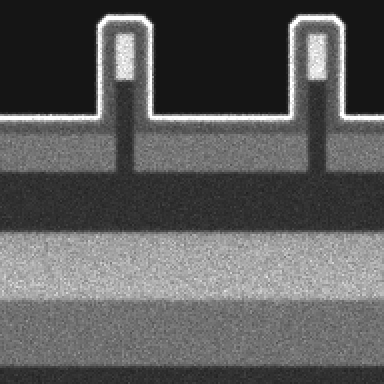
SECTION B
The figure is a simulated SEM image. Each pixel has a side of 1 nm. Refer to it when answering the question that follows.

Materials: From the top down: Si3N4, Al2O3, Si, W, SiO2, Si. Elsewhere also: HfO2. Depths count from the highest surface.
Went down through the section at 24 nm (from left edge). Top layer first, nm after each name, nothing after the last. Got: empty 100, Si3N4 18, Al2O3 38, Si 60, W 68, SiO2 66, Si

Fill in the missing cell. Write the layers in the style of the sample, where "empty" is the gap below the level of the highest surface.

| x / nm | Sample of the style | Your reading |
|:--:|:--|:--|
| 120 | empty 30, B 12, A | Si3N4 18, HfO2 46, Si 152, W 68, SiO2 66, Si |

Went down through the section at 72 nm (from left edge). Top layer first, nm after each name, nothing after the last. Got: empty 100, Si3N4 18, Al2O3 38, Si 60, W 68, SiO2 66, Si